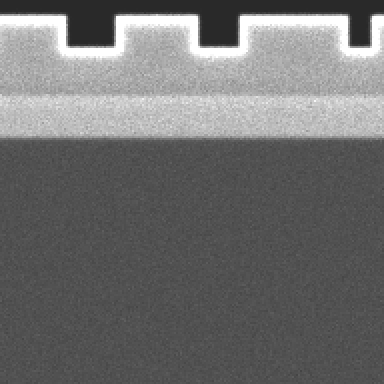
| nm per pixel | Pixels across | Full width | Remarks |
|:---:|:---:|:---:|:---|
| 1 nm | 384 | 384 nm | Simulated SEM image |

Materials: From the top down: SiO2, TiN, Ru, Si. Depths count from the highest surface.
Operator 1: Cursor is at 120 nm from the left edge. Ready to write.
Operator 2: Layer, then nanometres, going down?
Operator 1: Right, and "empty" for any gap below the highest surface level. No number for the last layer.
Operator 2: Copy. SiO2 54, TiN 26, Ru 42, Si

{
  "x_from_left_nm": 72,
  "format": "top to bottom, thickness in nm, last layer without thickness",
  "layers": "empty 32, SiO2 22, TiN 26, Ru 42, Si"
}